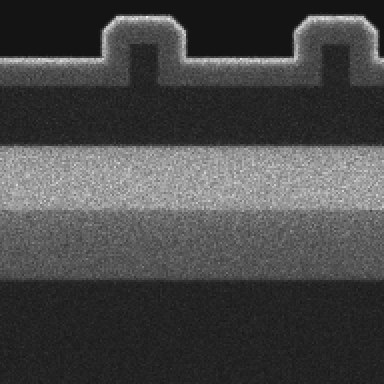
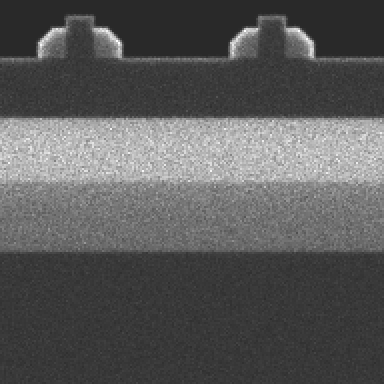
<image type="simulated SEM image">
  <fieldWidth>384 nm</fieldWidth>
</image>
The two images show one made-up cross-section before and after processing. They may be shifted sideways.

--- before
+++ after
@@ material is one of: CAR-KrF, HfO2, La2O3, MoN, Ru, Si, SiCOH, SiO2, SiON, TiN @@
SiO2 removed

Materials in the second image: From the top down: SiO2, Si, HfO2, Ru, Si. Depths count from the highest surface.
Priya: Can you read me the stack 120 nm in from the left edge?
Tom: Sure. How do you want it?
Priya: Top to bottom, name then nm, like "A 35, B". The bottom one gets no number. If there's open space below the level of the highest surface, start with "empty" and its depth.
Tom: empty 26, SiO2 16, Si 60, HfO2 64, Ru 70, Si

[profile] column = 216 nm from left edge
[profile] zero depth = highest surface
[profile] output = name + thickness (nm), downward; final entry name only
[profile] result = empty 42, Si 60, HfO2 64, Ru 70, Si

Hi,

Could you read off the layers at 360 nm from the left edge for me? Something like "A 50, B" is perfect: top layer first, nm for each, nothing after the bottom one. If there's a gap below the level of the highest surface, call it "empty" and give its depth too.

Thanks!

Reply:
empty 42, Si 60, HfO2 64, Ru 70, Si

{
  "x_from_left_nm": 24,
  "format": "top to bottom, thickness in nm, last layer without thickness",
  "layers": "empty 42, Si 60, HfO2 64, Ru 70, Si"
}